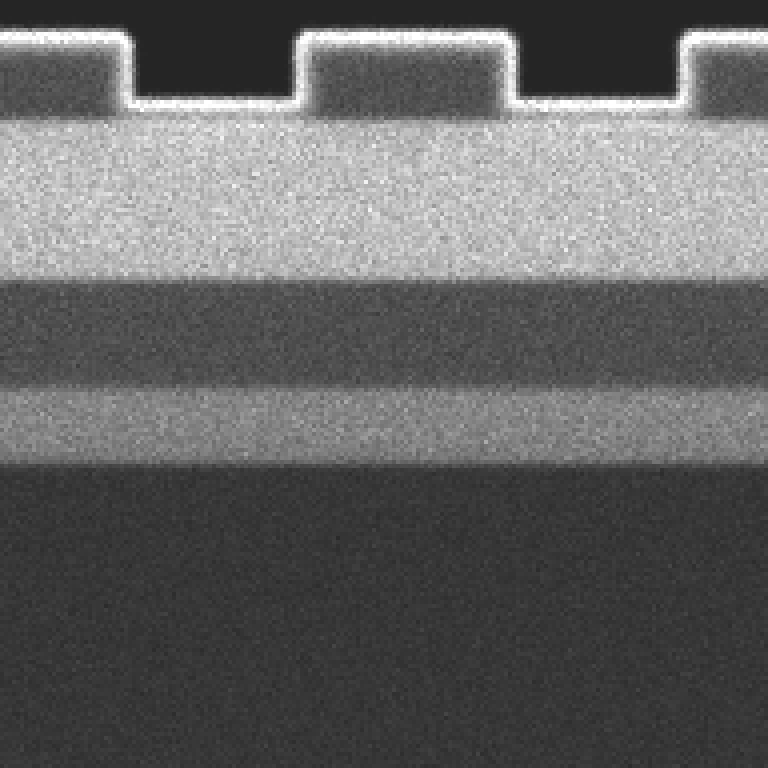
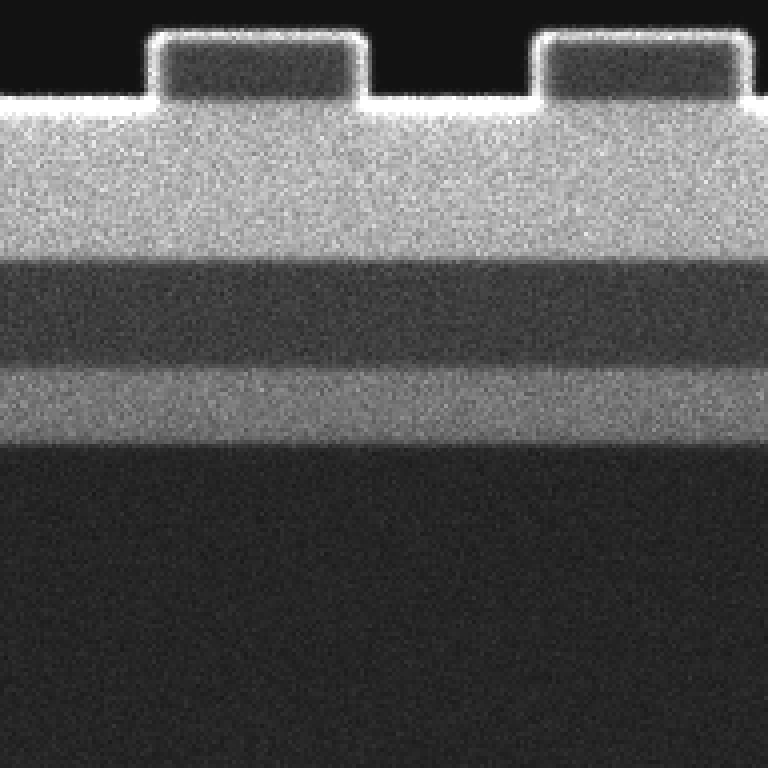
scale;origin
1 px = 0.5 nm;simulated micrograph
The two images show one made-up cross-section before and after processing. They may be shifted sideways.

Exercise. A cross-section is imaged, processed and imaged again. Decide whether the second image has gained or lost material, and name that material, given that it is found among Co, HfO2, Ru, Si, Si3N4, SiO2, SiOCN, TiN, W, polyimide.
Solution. removed: SiO2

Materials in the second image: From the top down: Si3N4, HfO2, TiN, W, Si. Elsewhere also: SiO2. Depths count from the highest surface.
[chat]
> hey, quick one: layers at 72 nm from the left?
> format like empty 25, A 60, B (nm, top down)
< empty 34, HfO2 80, TiN 54, W 38, Si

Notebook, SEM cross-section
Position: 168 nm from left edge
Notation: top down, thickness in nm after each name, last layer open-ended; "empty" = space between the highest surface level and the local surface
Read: Si3N4 34, HfO2 80, TiN 54, W 38, Si